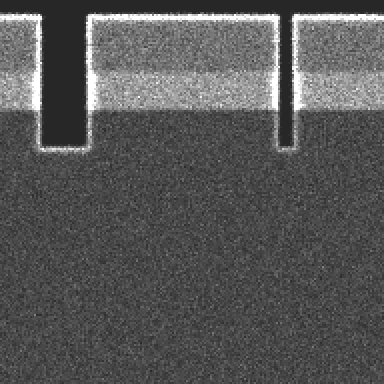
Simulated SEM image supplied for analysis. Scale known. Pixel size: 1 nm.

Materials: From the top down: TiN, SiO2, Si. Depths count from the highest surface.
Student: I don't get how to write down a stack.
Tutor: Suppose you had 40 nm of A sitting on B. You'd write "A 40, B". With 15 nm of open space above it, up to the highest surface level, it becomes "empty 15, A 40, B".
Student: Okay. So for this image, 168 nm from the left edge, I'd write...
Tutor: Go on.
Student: TiN 56, SiO2 38, Si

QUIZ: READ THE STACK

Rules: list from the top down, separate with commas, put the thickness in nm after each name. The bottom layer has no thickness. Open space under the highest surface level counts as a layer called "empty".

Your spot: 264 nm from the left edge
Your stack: TiN 56, SiO2 38, Si